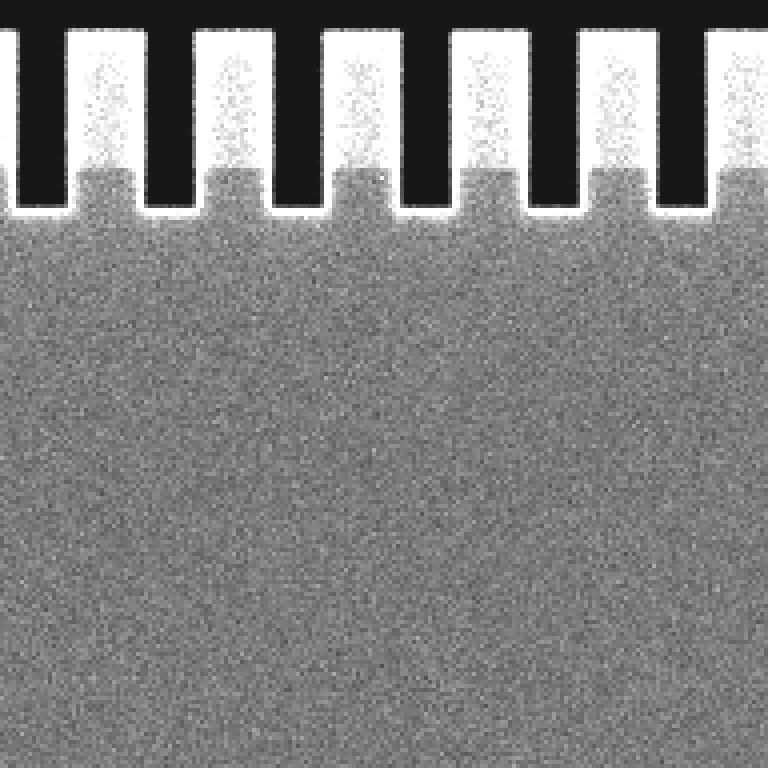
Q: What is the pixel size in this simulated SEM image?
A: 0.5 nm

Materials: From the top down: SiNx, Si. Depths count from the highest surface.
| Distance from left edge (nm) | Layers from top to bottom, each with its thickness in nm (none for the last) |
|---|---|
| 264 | empty 88, Si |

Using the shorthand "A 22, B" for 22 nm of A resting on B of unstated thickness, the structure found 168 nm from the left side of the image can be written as SiNx 68, Si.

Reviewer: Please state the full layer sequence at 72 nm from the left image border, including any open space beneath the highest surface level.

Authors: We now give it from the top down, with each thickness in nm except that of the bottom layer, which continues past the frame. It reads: empty 88, Si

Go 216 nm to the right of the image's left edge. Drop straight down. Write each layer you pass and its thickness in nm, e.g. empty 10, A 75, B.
empty 88, Si